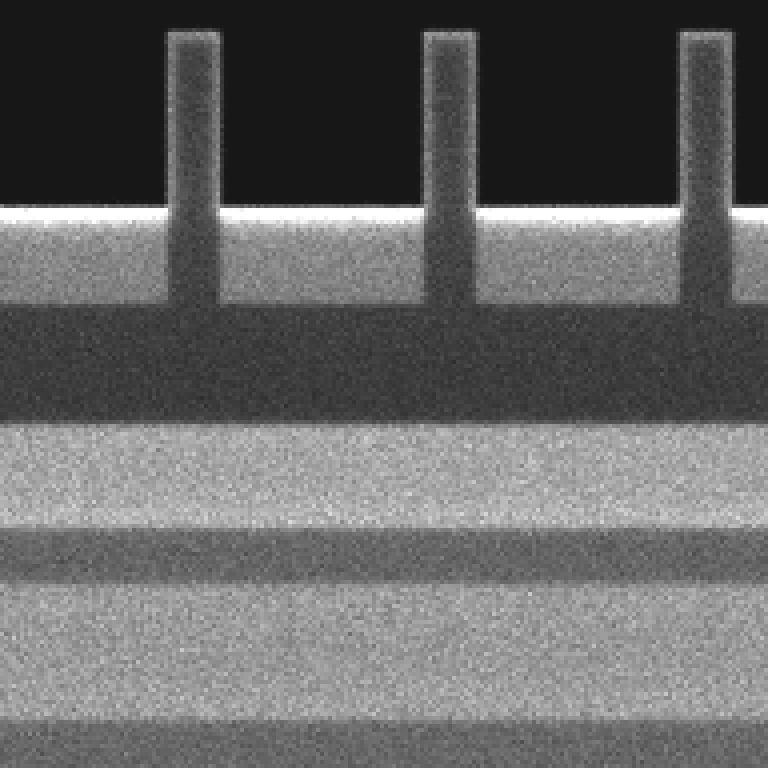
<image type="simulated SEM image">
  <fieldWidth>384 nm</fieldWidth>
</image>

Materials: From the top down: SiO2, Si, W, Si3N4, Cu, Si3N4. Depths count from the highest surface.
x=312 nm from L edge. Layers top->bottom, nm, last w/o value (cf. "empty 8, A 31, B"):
empty 88, SiO2 48, Si 60, W 52, Si3N4 28, Cu 68, Si3N4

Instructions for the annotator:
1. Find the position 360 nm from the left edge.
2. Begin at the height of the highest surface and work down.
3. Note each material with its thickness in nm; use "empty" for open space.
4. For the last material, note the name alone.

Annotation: Si 196, W 52, Si3N4 28, Cu 68, Si3N4